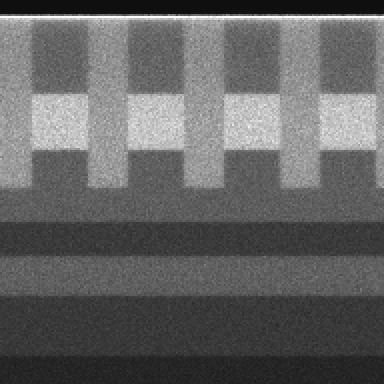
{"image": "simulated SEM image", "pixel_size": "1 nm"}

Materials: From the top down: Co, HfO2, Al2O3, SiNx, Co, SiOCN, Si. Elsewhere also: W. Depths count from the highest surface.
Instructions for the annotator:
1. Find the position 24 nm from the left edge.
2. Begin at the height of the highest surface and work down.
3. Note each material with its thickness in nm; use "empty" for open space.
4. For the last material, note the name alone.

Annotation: W 172, Al2O3 34, SiNx 34, Co 40, SiOCN 60, Si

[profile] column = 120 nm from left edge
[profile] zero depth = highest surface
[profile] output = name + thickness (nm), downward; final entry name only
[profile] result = W 172, Al2O3 34, SiNx 34, Co 40, SiOCN 60, Si